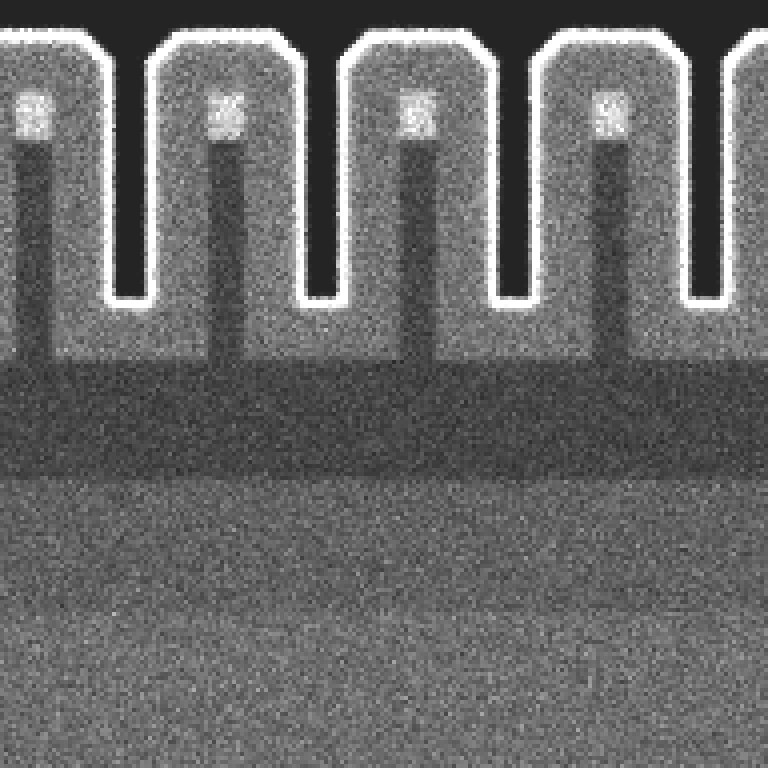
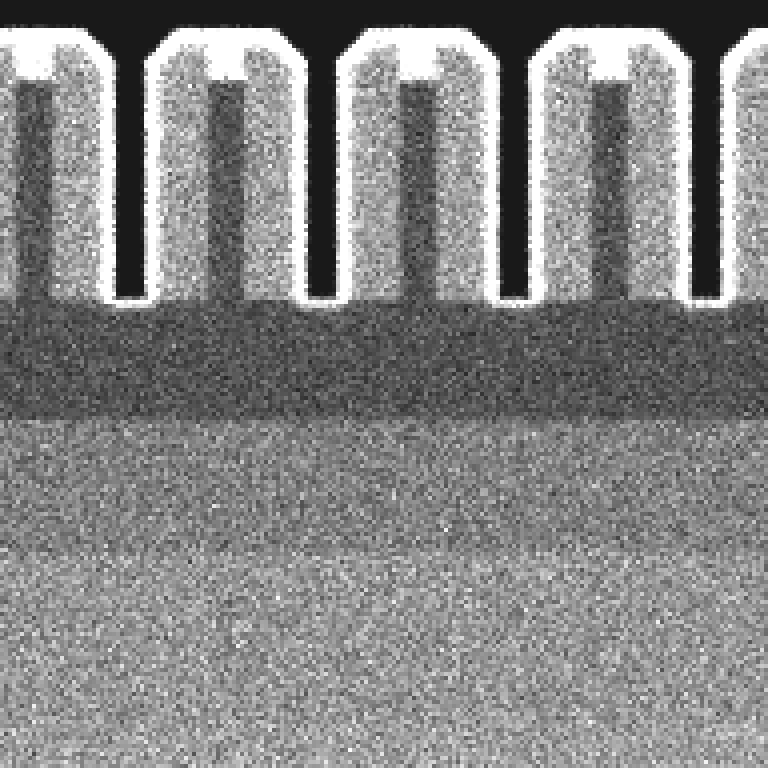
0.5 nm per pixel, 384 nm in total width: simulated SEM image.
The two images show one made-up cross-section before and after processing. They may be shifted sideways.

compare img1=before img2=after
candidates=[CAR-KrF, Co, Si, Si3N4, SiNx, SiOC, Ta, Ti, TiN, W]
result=removed:Si3N4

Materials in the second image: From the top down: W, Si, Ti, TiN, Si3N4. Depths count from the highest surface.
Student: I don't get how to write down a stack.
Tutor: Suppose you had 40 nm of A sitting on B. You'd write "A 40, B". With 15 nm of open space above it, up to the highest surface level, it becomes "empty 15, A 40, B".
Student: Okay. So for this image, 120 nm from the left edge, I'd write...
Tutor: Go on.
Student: W 24, Si 170, Ti 66, TiN 86, Si3N4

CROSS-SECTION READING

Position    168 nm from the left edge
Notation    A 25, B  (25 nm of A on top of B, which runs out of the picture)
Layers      empty 134, Si 60, Ti 66, TiN 86, Si3N4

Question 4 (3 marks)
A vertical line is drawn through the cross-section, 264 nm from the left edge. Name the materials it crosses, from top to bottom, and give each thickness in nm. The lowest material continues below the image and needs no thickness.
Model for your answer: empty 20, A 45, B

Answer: empty 134, Si 60, Ti 66, TiN 86, Si3N4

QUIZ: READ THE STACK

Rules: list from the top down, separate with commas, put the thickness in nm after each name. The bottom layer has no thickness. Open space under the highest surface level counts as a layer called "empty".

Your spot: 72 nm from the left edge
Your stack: empty 134, Si 60, Ti 66, TiN 86, Si3N4